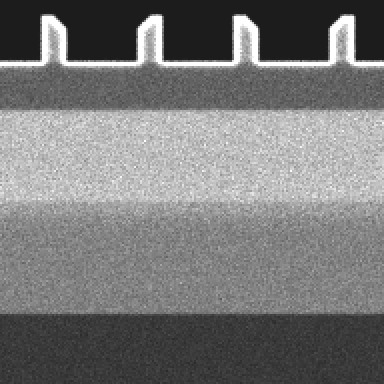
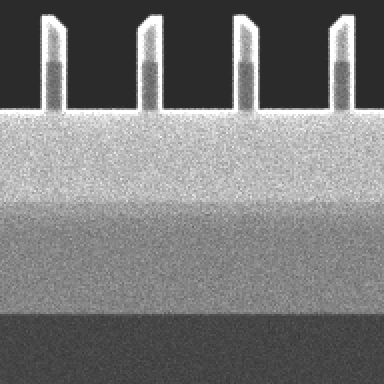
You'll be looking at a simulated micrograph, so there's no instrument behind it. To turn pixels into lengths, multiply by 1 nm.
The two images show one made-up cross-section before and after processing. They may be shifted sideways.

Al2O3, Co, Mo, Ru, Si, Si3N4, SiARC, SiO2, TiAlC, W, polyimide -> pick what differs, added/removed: Si3N4 removed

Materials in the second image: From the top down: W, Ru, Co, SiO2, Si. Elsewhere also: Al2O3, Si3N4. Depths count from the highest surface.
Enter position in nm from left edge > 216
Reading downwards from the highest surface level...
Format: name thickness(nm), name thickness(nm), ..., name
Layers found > empty 94, W 92, Ru 14, Co 12, SiO2 86, Si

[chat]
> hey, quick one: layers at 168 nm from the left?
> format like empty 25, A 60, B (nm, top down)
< empty 94, W 92, Ru 14, Co 12, SiO2 86, Si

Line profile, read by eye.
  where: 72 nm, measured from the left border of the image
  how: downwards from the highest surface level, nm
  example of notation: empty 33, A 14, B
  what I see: empty 94, W 92, Ru 14, Co 12, SiO2 86, Si